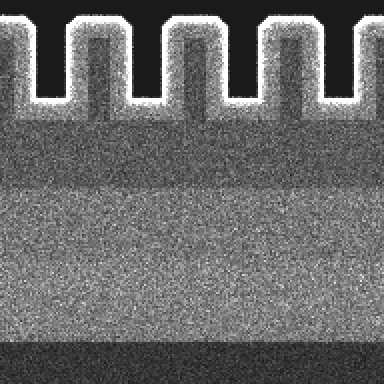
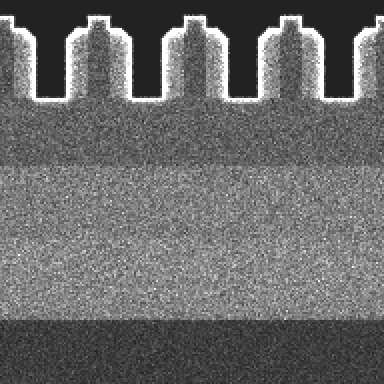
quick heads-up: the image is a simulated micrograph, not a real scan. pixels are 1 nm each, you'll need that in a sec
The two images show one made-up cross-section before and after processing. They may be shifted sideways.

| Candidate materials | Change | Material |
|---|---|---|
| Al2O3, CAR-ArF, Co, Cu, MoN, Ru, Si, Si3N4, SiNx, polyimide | removed | Al2O3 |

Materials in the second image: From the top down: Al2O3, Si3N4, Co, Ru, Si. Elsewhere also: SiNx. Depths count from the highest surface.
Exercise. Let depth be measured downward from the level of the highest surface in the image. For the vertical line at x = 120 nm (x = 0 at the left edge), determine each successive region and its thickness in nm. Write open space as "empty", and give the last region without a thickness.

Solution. empty 12, Al2O3 70, Si3N4 68, Co 74, Ru 80, Si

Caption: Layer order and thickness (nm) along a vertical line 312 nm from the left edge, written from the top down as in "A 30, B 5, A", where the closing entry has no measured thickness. empty 12, Al2O3 70, Si3N4 68, Co 74, Ru 80, Si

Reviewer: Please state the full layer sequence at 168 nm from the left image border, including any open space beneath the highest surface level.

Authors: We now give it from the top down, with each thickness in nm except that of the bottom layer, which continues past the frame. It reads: empty 16, Al2O3 66, Si3N4 68, Co 74, Ru 80, Si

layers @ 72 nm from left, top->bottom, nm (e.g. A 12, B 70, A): empty 16, Al2O3 66, Si3N4 68, Co 74, Ru 80, Si